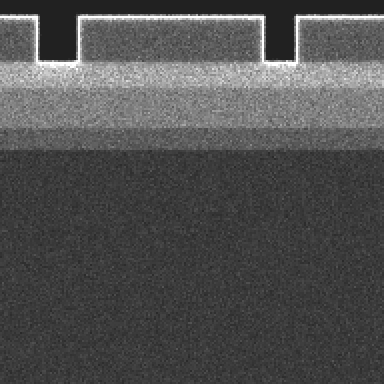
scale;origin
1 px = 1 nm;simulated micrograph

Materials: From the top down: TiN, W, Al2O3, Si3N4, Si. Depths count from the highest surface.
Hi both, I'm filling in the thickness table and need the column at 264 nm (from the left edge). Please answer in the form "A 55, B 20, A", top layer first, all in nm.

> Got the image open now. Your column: empty 46, W 26, Al2O3 40, Si3N4 22, Si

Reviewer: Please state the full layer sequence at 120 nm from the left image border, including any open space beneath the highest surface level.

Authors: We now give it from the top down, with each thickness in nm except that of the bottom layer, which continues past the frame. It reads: TiN 46, W 26, Al2O3 40, Si3N4 22, Si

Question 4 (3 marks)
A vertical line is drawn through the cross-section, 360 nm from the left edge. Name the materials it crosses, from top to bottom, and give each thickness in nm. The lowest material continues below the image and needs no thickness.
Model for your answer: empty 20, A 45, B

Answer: TiN 46, W 26, Al2O3 40, Si3N4 22, Si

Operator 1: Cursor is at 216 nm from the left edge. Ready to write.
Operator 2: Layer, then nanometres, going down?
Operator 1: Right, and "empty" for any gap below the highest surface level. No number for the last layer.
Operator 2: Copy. TiN 46, W 26, Al2O3 40, Si3N4 22, Si